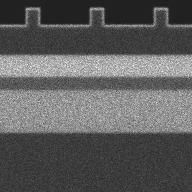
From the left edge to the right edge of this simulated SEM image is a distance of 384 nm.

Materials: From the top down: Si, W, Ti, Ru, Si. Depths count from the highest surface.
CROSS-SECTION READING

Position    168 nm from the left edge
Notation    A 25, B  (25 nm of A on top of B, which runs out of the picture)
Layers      empty 34, Si 60, W 44, Ti 26, Ru 86, Si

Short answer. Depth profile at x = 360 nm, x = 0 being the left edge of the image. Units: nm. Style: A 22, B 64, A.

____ empty 34, Si 60, W 44, Ti 26, Ru 86, Si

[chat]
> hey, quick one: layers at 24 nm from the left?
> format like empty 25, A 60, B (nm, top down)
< empty 34, Si 60, W 44, Ti 26, Ru 86, Si